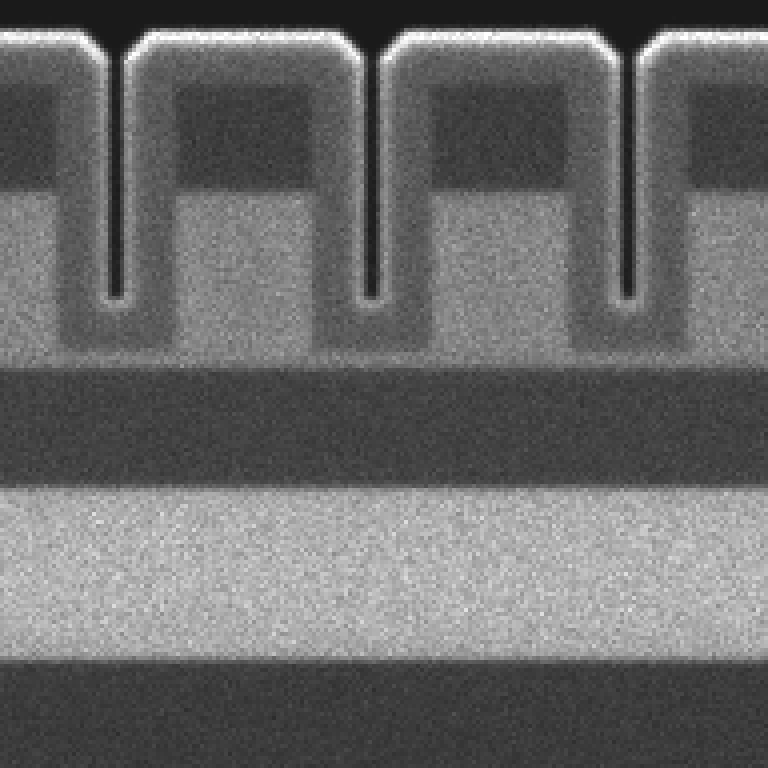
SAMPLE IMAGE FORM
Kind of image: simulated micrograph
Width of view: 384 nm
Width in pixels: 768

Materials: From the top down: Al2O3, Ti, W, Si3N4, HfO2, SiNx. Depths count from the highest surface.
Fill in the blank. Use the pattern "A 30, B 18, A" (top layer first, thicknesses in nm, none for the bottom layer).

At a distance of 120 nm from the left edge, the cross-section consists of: Al2O3 26, Ti 54, W 88, Si3N4 60, HfO2 86, SiNx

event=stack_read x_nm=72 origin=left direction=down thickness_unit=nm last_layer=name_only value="empty 2, Al2O3 158, W 8, Si3N4 60, HfO2 86, SiNx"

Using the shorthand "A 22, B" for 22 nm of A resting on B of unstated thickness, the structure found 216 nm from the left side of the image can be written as Al2O3 26, Ti 54, W 88, Si3N4 60, HfO2 86, SiNx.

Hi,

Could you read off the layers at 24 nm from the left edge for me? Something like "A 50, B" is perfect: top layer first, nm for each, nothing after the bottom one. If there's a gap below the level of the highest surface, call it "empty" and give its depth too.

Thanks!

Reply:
Al2O3 26, Ti 54, W 88, Si3N4 60, HfO2 86, SiNx